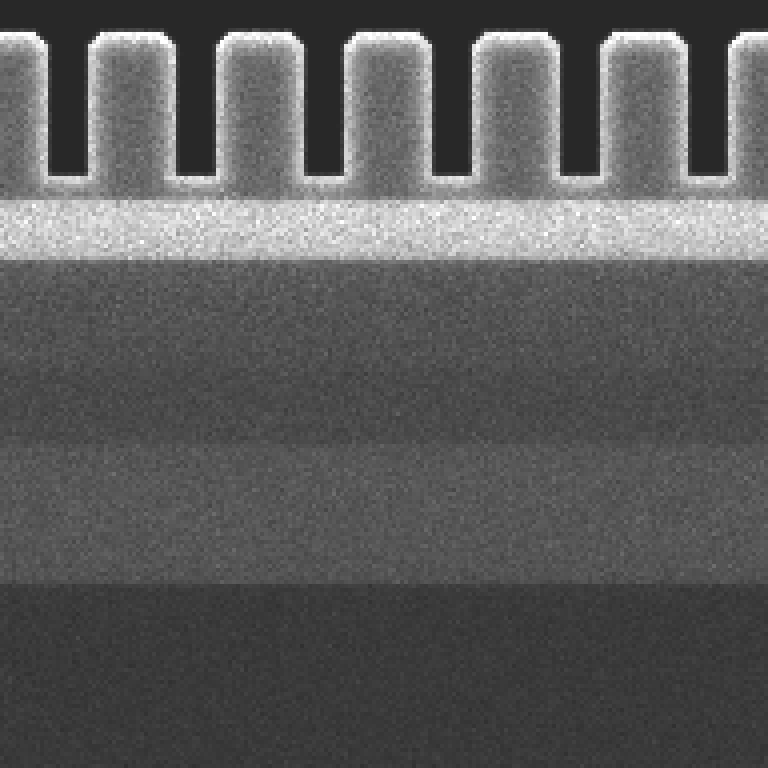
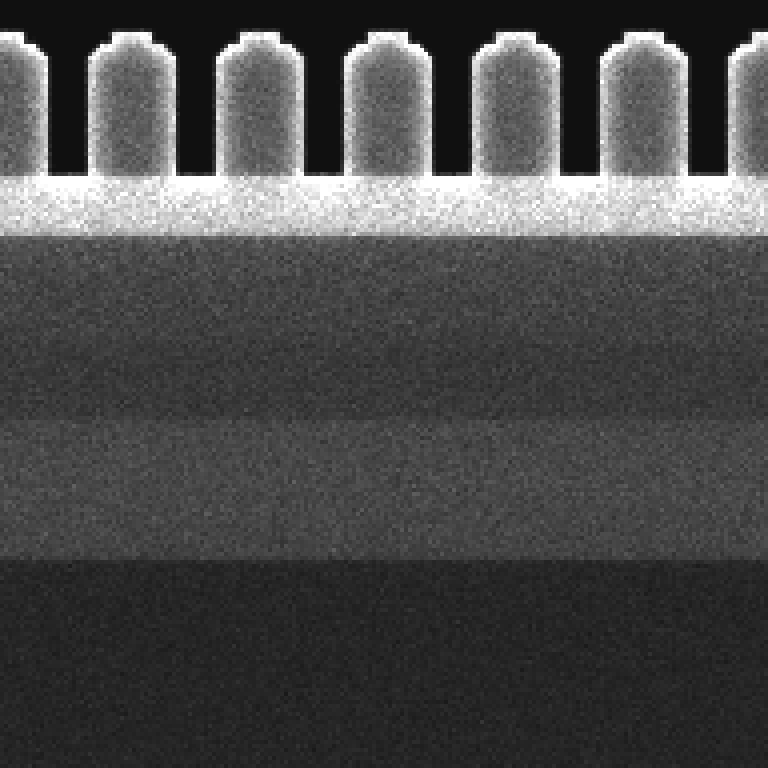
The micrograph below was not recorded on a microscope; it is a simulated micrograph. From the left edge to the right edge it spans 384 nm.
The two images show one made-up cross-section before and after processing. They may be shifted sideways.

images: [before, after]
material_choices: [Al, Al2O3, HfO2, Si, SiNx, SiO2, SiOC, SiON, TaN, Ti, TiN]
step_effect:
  removed: Al2O3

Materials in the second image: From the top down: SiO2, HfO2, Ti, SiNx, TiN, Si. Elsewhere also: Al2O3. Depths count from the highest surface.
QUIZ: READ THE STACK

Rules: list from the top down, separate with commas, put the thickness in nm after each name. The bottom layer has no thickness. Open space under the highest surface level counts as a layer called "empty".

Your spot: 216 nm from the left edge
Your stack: empty 72, HfO2 30, Ti 54, SiNx 38, TiN 70, Si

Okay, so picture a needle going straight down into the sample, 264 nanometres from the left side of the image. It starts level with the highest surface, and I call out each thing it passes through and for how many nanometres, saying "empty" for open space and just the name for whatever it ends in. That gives SiO2 72, HfO2 30, Ti 54, SiNx 38, TiN 70, Si